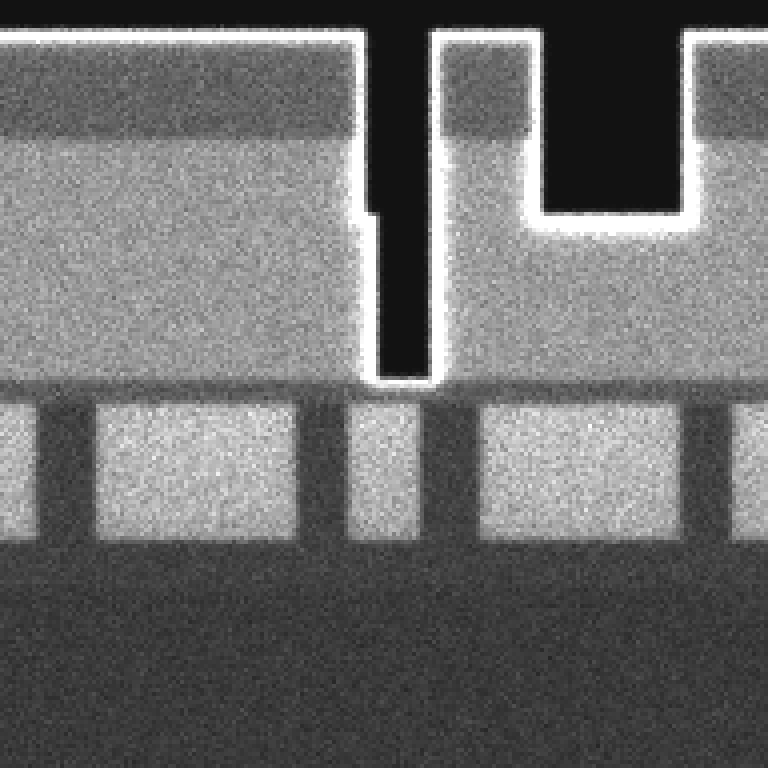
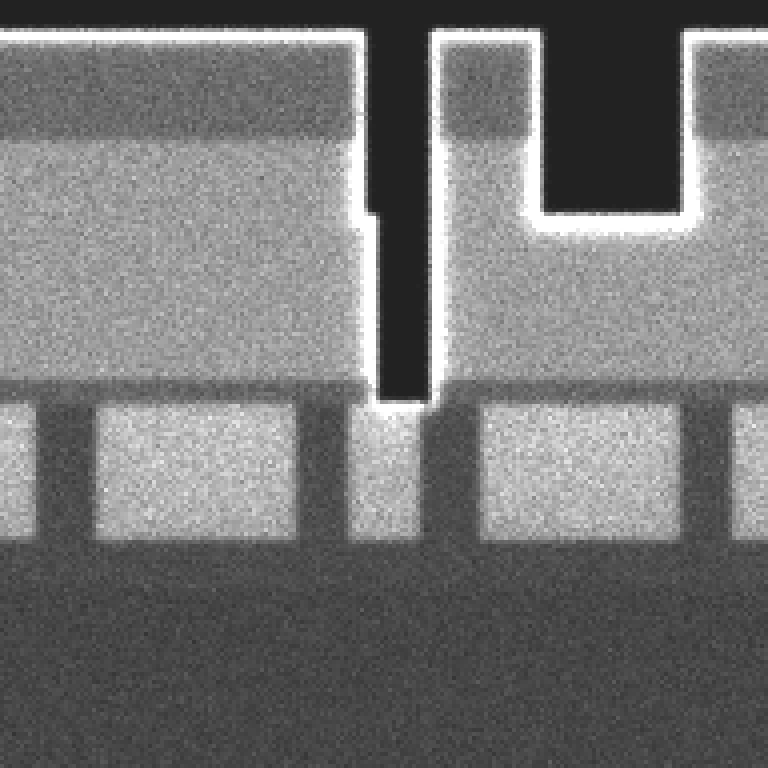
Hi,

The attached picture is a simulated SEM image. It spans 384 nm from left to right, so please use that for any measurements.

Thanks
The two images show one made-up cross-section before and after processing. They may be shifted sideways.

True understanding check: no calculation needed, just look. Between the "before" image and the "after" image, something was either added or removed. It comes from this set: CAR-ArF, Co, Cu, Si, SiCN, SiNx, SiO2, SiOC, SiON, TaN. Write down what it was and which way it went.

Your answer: SiCN (removed)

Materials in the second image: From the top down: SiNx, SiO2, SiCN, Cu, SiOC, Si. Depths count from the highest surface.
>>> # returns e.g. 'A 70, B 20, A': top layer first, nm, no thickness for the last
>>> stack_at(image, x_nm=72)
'SiNx 54, SiO2 120, SiCN 12, Cu 68, SiOC 24, Si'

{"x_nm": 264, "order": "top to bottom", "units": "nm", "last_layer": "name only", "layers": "SiNx 54, SiO2 120, SiCN 12, Cu 68, SiOC 24, Si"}